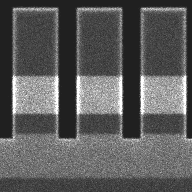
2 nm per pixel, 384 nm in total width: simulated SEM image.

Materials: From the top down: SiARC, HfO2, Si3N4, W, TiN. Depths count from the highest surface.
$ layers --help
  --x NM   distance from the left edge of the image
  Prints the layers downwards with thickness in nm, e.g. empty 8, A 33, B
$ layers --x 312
SiARC 136, HfO2 76, Si3N4 40, W 88, TiN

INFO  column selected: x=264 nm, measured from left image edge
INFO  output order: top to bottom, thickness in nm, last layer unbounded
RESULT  empty 262, W 78, TiN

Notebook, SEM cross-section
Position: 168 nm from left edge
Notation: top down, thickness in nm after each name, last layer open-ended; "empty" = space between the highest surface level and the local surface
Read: SiARC 136, HfO2 76, Si3N4 40, W 88, TiN